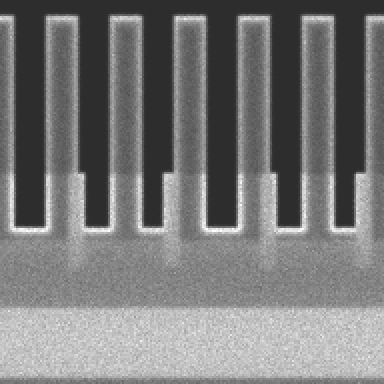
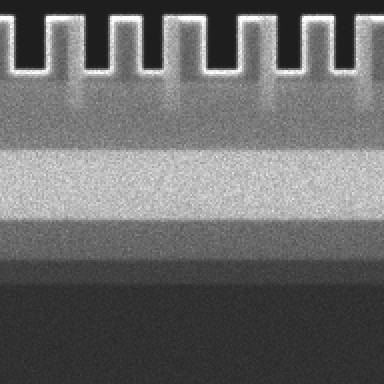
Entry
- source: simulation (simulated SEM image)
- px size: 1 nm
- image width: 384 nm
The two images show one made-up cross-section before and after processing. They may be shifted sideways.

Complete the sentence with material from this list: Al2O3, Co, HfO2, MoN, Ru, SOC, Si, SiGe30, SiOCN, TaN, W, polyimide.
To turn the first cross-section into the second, SOC must be removed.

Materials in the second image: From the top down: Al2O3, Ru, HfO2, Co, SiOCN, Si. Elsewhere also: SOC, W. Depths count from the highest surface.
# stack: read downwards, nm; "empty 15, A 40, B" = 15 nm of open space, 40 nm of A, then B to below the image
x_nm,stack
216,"empty 54, Al2O3 12, Ru 68, HfO2 70, Co 40, SiOCN 24, Si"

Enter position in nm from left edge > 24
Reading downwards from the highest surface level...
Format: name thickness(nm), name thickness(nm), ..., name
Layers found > empty 54, Al2O3 12, Ru 68, HfO2 70, Co 40, SiOCN 24, Si